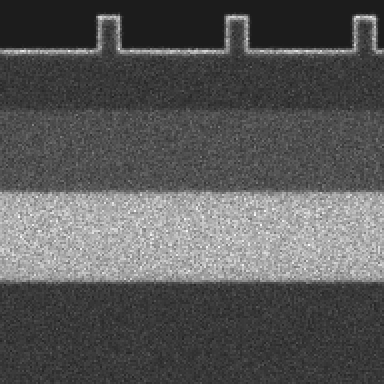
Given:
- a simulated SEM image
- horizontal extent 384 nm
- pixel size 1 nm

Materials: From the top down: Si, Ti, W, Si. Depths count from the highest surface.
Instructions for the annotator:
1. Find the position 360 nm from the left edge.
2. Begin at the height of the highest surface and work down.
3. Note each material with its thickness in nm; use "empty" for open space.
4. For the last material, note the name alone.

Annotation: Si 94, Ti 82, W 90, Si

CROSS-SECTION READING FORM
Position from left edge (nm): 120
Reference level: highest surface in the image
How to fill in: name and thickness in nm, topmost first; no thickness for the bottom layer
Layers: empty 34, Si 60, Ti 82, W 90, Si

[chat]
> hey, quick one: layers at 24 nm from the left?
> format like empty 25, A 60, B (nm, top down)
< empty 34, Si 60, Ti 82, W 90, Si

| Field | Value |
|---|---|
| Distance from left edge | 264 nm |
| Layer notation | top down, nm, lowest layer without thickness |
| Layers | empty 34, Si 60, Ti 82, W 90, Si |